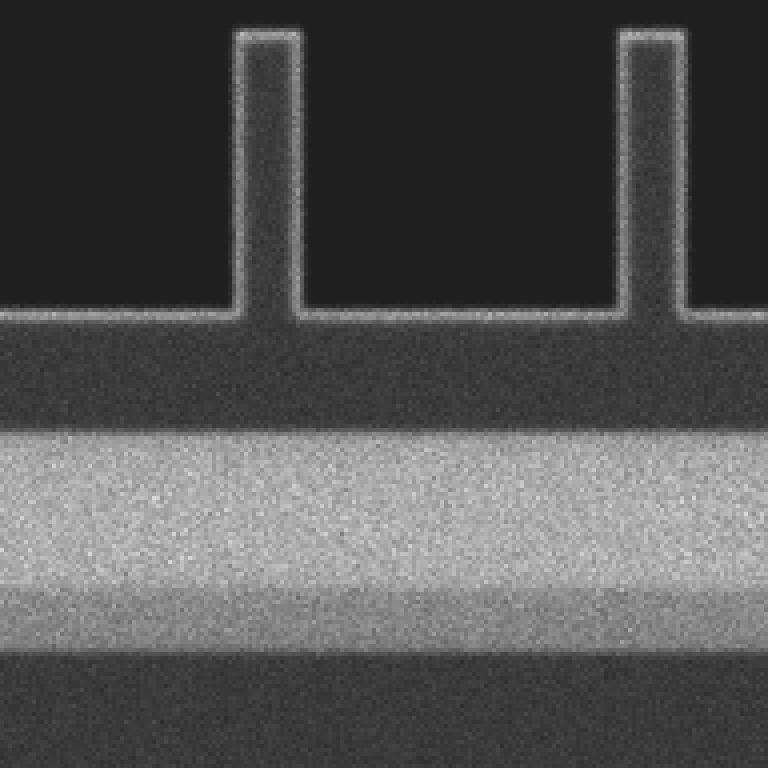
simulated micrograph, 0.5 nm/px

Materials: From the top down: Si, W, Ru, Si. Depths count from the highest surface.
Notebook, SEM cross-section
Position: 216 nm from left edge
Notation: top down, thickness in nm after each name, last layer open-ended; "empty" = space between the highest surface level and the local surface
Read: empty 140, Si 60, W 78, Ru 32, Si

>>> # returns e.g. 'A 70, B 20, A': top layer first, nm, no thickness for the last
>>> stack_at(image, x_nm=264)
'empty 140, Si 60, W 78, Ru 32, Si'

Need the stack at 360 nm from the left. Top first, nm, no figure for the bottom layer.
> empty 140, Si 60, W 78, Ru 32, Si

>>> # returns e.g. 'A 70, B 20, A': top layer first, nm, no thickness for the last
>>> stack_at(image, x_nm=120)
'Si 200, W 78, Ru 32, Si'